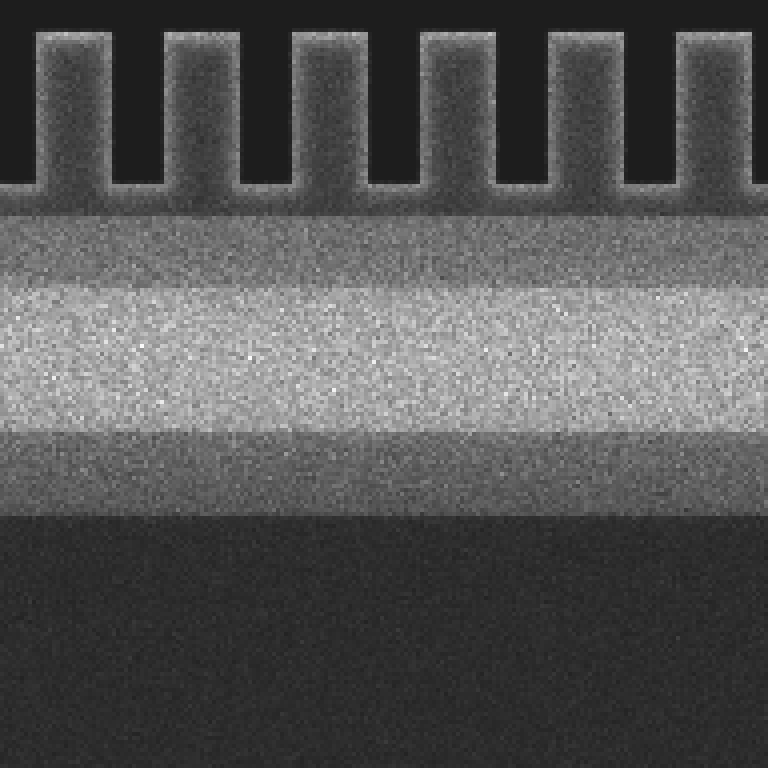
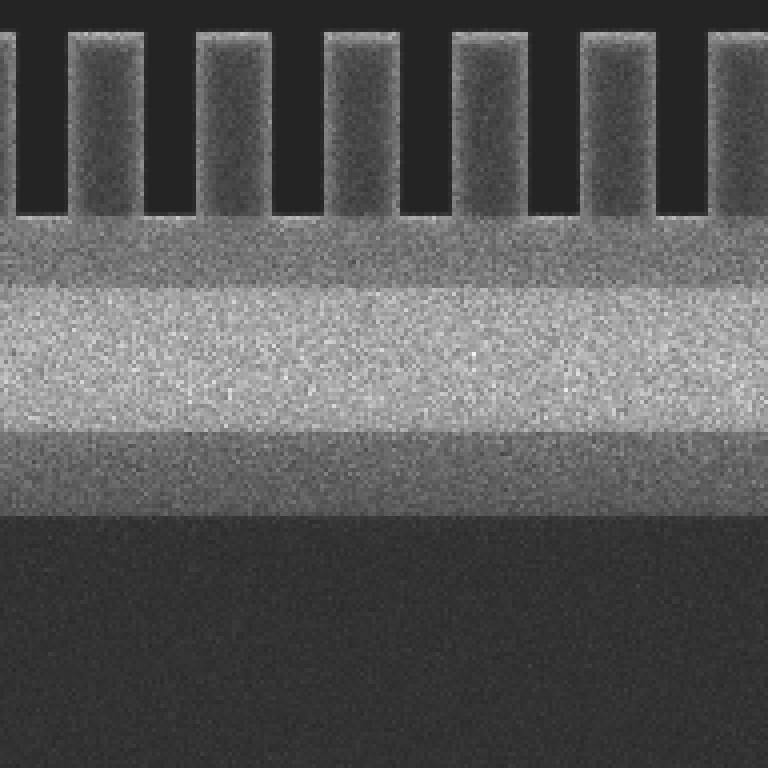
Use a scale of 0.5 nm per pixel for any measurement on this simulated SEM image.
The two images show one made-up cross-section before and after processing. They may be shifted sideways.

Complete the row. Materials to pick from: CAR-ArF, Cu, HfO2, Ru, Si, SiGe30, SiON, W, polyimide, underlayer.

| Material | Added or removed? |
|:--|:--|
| underlayer | removed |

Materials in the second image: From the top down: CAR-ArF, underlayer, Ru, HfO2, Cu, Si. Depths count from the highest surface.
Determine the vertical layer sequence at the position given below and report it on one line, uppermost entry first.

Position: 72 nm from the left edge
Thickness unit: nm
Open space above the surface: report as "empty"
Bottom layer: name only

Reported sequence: empty 92, Ru 36, HfO2 72, Cu 42, Si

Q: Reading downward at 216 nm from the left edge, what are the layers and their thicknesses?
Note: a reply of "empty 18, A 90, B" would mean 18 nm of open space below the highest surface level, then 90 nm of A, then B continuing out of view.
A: empty 92, Ru 36, HfO2 72, Cu 42, Si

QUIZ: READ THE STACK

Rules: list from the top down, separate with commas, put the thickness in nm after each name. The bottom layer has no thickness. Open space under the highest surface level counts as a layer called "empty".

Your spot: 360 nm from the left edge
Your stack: CAR-ArF 76, underlayer 16, Ru 36, HfO2 72, Cu 42, Si